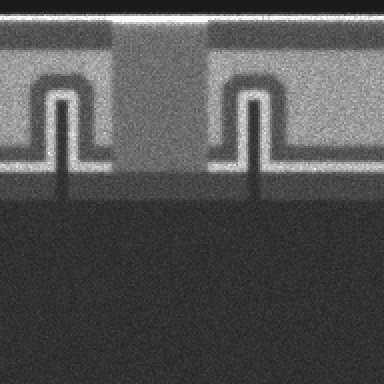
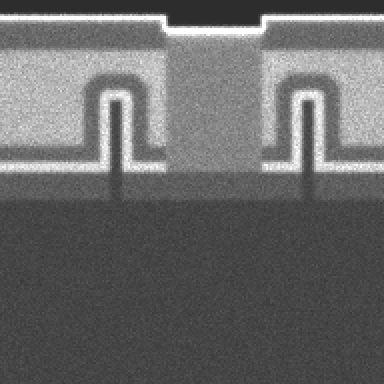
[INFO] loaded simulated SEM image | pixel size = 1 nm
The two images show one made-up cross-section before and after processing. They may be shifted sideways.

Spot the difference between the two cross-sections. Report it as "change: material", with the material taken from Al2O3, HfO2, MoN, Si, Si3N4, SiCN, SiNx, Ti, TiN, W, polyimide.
removed: Al2O3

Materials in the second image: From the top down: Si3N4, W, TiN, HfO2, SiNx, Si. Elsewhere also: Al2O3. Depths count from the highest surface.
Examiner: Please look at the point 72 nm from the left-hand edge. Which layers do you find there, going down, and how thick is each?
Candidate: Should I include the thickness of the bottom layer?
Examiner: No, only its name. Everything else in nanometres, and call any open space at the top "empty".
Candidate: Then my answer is Si3N4 34, W 96, TiN 16, HfO2 10, SiNx 28, Si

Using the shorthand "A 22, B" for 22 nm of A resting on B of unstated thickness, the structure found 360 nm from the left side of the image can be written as Si3N4 34, W 96, TiN 16, HfO2 10, SiNx 28, Si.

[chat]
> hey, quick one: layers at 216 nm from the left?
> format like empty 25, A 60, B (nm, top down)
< empty 12, Al2O3 144, SiNx 28, Si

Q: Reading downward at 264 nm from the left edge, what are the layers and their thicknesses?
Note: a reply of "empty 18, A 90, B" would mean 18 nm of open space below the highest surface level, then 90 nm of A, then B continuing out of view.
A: Si3N4 34, W 96, TiN 16, HfO2 10, SiNx 28, Si